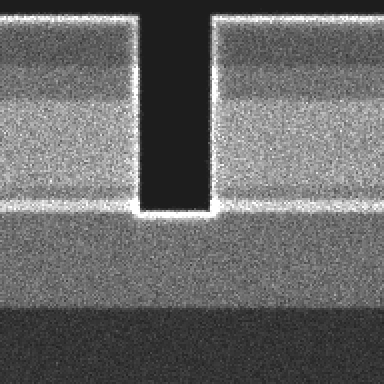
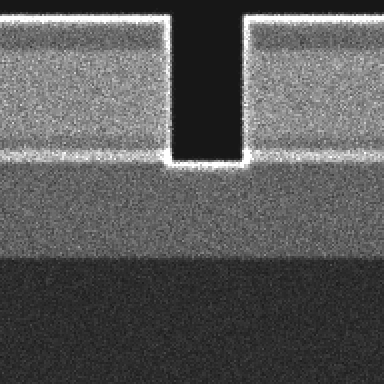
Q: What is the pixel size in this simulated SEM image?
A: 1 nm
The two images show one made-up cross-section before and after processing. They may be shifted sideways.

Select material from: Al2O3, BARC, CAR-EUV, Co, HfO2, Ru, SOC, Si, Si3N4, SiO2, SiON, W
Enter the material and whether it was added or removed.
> SOC / removed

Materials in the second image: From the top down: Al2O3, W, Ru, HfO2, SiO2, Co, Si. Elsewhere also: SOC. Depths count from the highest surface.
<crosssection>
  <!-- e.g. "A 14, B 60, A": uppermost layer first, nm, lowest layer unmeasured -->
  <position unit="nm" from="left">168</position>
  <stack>Al2O3 34, W 86, Ru 14, HfO2 12, SiO2 64, Co 32, Si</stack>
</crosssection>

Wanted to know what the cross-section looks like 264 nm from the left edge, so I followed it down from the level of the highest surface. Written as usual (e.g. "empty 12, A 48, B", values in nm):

Al2O3 34, W 86, Ru 14, HfO2 12, SiO2 64, Co 32, Si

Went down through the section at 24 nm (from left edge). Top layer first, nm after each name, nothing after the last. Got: Al2O3 34, W 86, Ru 14, HfO2 12, SiO2 64, Co 32, Si